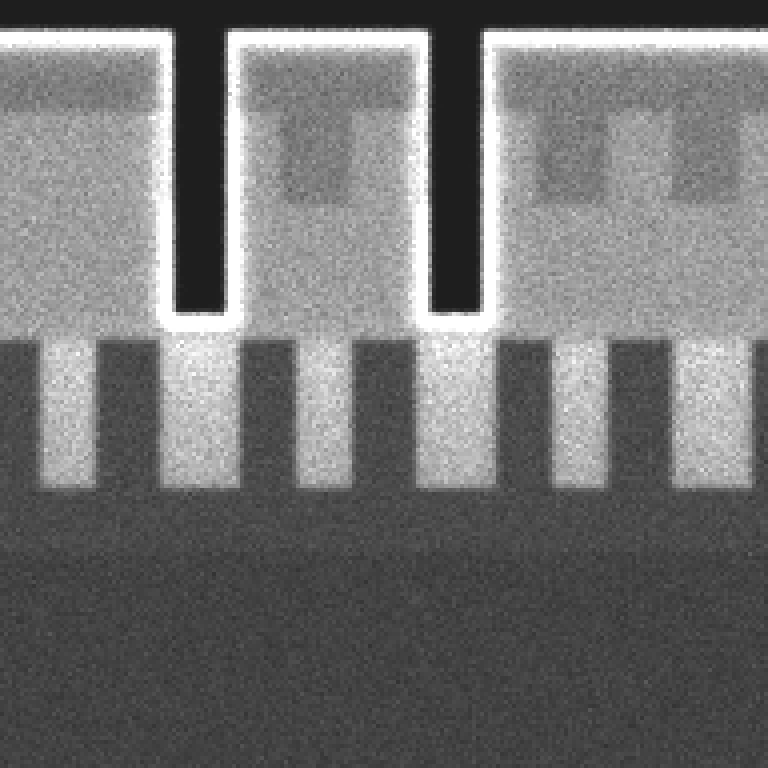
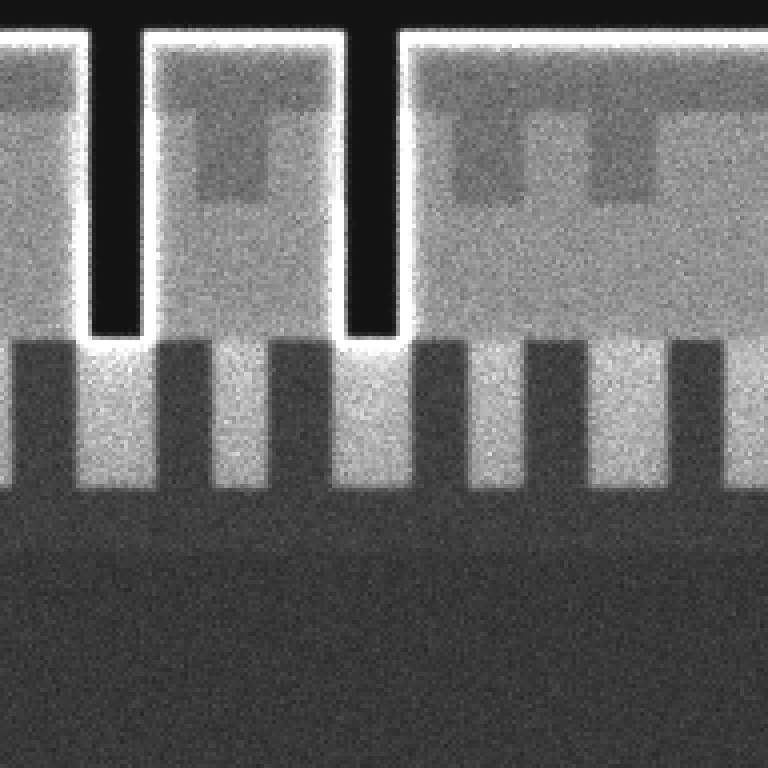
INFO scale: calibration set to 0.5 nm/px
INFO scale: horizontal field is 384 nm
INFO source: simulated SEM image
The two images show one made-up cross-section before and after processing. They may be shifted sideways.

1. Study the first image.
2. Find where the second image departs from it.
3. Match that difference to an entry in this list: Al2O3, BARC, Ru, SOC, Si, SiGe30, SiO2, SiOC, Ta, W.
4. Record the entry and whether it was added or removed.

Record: Al2O3 / removed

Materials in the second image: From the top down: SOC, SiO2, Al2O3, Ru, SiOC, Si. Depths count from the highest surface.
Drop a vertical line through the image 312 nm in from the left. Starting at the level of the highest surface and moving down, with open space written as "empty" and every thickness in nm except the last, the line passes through SOC 86, SiO2 56, Al2O3 12, Ru 74, SiOC 32, Si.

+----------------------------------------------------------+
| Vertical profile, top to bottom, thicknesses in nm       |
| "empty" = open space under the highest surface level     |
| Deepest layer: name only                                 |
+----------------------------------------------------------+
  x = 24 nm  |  SOC 40, SiO2 102, Al2O3 12, SiOC 106, Si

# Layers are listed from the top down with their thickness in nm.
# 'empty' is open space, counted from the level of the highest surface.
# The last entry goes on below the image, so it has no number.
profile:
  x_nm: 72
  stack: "SOC 40, SiO2 102, Al2O3 12, Ru 74, SiOC 32, Si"